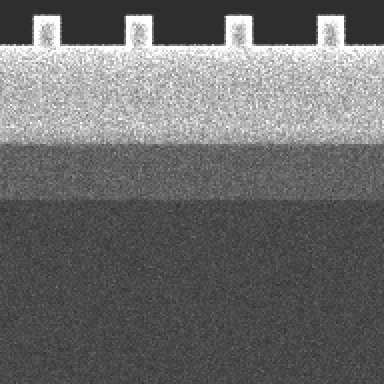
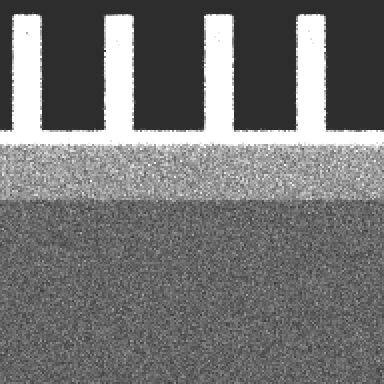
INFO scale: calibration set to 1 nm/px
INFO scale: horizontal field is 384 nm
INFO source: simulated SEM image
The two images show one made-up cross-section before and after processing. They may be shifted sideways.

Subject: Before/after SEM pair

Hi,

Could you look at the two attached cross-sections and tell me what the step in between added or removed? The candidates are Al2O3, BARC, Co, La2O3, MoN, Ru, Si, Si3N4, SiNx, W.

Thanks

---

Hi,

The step removed W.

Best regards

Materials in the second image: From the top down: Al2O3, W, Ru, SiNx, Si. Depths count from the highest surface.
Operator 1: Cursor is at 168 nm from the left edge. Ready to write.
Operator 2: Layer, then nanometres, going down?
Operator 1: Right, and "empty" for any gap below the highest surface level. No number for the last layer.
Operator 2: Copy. empty 116, Ru 12, SiNx 56, Si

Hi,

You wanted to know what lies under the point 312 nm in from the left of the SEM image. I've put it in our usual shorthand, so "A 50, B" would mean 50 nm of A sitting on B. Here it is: Al2O3 30, W 86, Ru 12, SiNx 56, Si